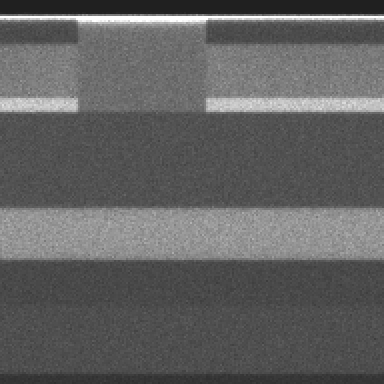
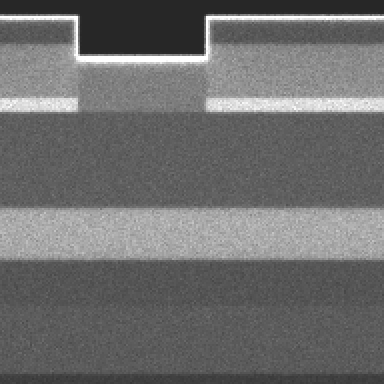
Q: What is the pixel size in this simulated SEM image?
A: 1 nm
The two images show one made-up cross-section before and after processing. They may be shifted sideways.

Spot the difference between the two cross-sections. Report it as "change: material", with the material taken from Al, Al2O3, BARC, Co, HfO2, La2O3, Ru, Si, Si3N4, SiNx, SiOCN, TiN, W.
removed: Al2O3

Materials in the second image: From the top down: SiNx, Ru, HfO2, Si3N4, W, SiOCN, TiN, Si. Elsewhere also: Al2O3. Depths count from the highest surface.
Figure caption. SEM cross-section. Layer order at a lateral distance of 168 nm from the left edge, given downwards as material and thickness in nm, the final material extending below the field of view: empty 40, Al2O3 56, Si3N4 96, W 52, SiOCN 46, TiN 68, Si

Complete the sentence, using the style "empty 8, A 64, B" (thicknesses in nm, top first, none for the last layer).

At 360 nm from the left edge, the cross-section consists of SiNx 28, Ru 54, HfO2 14, Si3N4 96, W 52, SiOCN 46, TiN 68, Si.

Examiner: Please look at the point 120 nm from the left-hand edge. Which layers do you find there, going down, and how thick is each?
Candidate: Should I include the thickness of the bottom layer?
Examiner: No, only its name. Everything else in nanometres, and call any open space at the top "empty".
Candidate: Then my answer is empty 40, Al2O3 56, Si3N4 96, W 52, SiOCN 46, TiN 68, Si